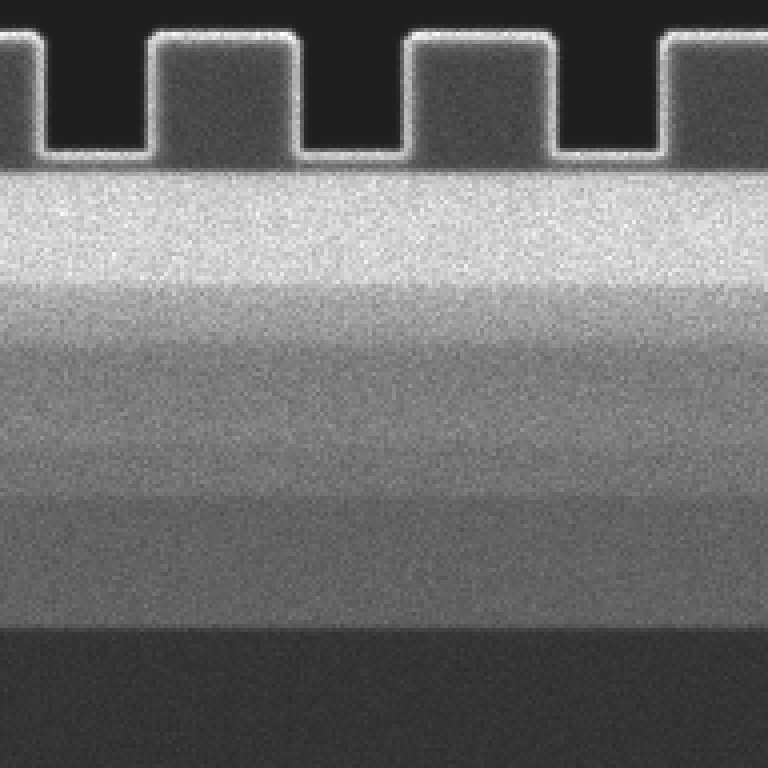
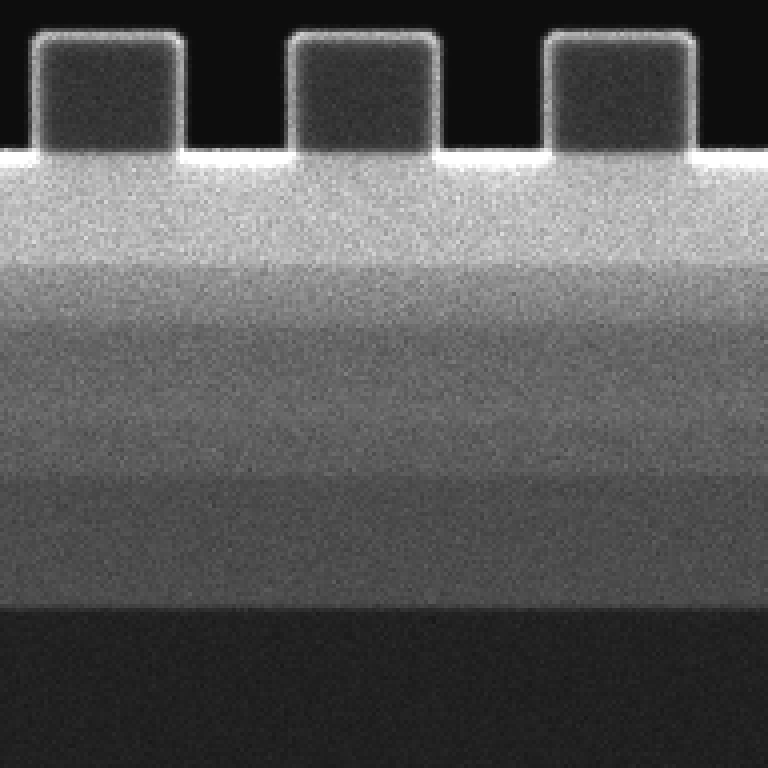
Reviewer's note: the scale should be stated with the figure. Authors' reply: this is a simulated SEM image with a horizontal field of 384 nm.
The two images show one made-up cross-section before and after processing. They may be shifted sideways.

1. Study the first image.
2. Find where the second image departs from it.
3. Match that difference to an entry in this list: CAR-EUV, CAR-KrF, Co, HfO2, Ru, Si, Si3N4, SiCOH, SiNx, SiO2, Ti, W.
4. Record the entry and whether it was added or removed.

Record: Si3N4 / removed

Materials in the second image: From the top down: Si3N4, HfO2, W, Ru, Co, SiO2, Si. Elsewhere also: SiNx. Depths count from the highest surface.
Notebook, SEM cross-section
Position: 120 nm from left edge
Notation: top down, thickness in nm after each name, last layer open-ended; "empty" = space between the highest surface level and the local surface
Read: empty 60, HfO2 56, W 30, Ru 50, Co 26, SiO2 66, Si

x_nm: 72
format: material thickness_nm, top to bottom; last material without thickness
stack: SiNx 60, HfO2 56, W 30, Ru 50, Co 26, SiO2 66, Si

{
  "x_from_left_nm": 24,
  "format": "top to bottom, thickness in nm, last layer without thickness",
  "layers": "Si3N4 60, HfO2 56, W 30, Ru 50, Co 26, SiO2 66, Si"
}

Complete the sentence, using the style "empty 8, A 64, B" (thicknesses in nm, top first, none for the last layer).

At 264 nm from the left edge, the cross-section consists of empty 60, HfO2 56, W 30, Ru 50, Co 26, SiO2 66, Si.